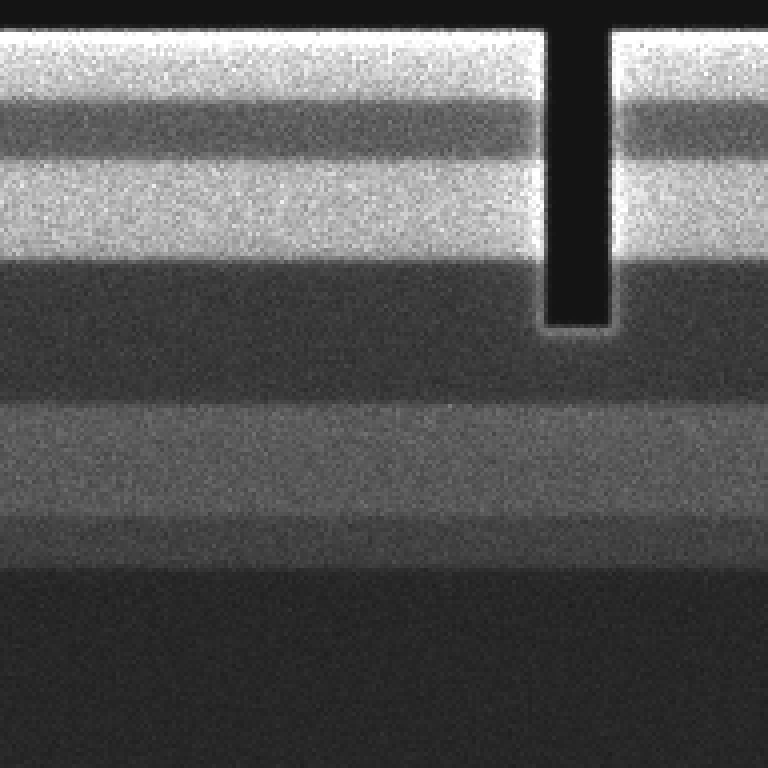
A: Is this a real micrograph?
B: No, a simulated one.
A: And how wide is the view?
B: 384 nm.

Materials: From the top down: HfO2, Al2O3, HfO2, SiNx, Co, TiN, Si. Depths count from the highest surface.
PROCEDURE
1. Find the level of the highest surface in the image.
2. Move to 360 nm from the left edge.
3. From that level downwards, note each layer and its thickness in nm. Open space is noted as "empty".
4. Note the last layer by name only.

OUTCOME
HfO2 34, Al2O3 30, HfO2 50, SiNx 72, Co 56, TiN 26, Si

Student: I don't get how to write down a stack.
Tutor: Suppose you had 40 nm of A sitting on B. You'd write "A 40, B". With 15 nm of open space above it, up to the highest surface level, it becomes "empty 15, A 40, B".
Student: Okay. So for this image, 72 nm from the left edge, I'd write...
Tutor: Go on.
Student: HfO2 34, Al2O3 30, HfO2 50, SiNx 72, Co 56, TiN 26, Si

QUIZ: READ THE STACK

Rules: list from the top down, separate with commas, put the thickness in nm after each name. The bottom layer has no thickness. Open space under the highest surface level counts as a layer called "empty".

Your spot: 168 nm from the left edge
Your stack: HfO2 34, Al2O3 30, HfO2 50, SiNx 72, Co 56, TiN 26, Si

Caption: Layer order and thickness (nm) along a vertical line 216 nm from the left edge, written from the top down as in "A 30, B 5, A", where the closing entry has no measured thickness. HfO2 34, Al2O3 30, HfO2 50, SiNx 72, Co 56, TiN 26, Si